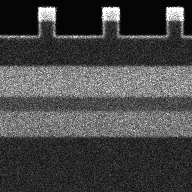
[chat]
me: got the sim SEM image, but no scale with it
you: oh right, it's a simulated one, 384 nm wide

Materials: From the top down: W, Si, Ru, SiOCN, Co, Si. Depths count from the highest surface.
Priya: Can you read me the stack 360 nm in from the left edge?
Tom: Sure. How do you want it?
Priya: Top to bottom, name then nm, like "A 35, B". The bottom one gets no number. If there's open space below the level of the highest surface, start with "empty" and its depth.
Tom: W 26, Si 90, Ru 62, SiOCN 28, Co 52, Si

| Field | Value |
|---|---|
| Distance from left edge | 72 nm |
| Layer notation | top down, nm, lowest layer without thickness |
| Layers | empty 56, Si 60, Ru 62, SiOCN 28, Co 52, Si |